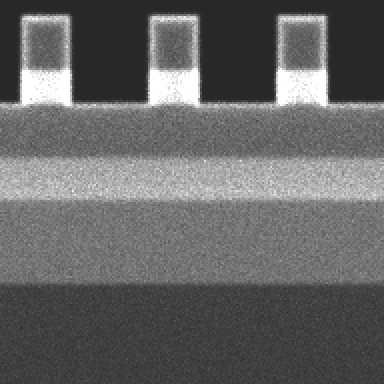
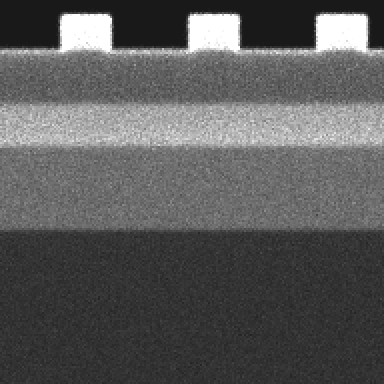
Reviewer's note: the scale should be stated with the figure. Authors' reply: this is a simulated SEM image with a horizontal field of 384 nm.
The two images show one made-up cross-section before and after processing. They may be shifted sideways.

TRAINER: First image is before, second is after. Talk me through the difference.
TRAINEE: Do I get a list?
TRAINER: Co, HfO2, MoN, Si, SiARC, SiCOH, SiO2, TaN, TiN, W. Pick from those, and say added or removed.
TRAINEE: removed: SiARC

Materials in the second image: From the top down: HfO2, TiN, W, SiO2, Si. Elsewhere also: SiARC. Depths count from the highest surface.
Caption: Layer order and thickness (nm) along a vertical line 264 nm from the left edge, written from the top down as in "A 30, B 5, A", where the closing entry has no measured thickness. empty 34, TiN 54, W 42, SiO2 84, Si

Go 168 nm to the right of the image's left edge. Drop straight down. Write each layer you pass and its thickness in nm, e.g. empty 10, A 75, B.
empty 34, TiN 54, W 42, SiO2 84, Si